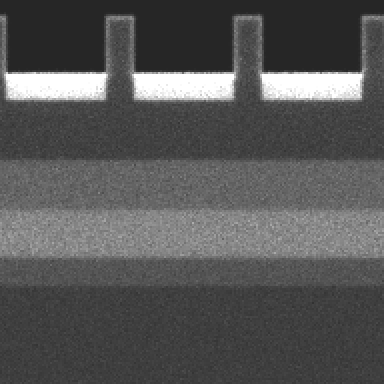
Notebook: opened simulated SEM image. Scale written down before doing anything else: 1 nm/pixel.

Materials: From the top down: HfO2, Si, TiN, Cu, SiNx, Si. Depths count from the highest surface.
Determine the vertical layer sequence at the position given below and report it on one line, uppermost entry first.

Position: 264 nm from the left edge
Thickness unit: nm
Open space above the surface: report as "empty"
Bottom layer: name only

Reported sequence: empty 58, HfO2 26, Si 60, TiN 50, Cu 48, SiNx 28, Si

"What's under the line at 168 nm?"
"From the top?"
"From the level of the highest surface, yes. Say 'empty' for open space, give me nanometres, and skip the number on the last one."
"empty 58, HfO2 26, Si 60, TiN 50, Cu 48, SiNx 28, Si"